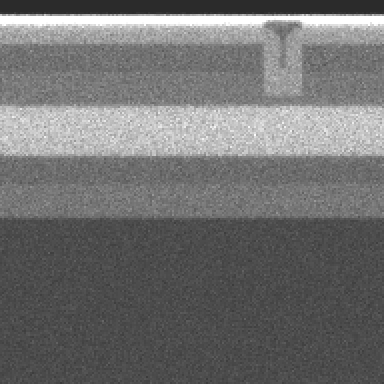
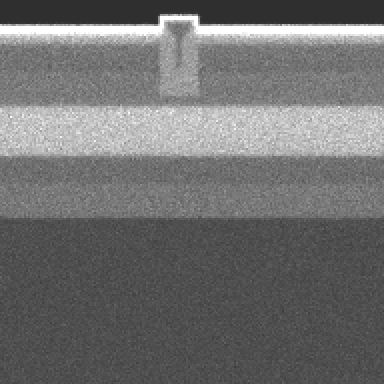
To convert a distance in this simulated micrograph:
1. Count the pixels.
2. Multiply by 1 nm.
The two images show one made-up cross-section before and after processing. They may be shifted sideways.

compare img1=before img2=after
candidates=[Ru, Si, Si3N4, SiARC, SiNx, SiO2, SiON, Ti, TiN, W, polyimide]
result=removed:SiO2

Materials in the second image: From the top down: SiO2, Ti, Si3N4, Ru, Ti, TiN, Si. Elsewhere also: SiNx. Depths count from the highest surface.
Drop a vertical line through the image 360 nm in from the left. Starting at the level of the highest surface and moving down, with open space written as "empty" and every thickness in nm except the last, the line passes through empty 10, SiO2 18, Ti 28, Si3N4 34, Ru 50, Ti 28, TiN 34, Si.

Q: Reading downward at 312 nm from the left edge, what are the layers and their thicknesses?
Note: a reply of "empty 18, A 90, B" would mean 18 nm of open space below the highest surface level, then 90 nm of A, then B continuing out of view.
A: empty 10, SiO2 18, Ti 28, Si3N4 34, Ru 50, Ti 28, TiN 34, Si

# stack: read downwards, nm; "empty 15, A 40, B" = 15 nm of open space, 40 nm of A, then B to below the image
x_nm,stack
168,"SiNx 14, SiO2 66, Si3N4 10, Ru 50, Ti 28, TiN 34, Si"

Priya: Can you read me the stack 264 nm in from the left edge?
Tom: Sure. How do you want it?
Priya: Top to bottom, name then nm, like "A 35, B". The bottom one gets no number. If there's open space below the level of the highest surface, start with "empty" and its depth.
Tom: empty 10, SiO2 18, Ti 28, Si3N4 34, Ru 50, Ti 28, TiN 34, Si